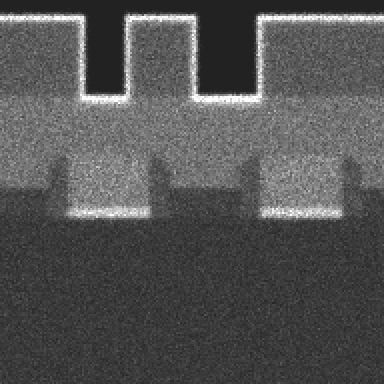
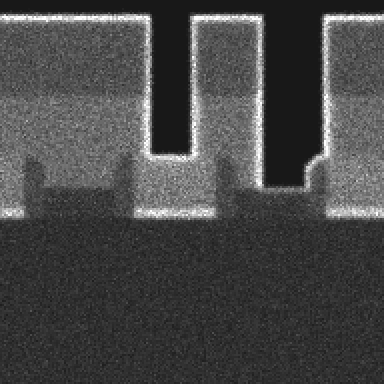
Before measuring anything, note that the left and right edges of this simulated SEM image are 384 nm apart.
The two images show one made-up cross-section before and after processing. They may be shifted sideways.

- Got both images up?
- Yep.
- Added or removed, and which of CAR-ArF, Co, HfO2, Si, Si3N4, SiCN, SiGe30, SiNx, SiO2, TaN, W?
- removed, SiO2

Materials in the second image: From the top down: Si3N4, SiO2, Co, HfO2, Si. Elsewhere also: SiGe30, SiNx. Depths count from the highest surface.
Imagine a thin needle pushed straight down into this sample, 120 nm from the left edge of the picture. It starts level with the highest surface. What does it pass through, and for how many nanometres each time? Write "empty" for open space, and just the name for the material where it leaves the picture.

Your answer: Si3N4 80, SiO2 64, SiNx 58, Si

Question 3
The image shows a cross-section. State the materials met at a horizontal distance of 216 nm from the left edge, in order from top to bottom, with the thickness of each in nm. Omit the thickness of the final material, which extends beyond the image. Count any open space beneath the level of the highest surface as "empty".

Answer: Si3N4 80, SiO2 60, SiNx 62, Si